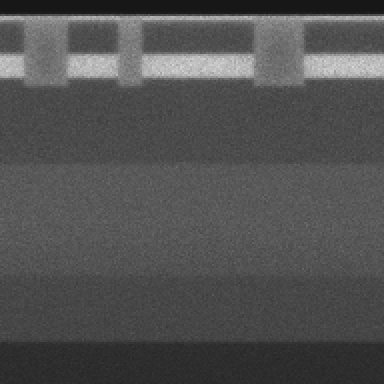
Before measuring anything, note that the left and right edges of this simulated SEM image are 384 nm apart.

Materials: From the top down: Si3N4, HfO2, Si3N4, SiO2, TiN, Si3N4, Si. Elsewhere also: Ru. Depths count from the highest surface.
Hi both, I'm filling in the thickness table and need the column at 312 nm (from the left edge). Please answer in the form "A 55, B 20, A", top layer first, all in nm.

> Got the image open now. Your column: Si3N4 38, HfO2 24, Si3N4 86, SiO2 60, TiN 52, Si3N4 66, Si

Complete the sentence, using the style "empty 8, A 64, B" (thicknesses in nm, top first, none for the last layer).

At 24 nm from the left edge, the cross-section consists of Ru 70, Si3N4 78, SiO2 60, TiN 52, Si3N4 66, Si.